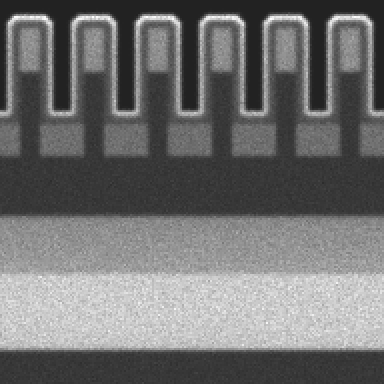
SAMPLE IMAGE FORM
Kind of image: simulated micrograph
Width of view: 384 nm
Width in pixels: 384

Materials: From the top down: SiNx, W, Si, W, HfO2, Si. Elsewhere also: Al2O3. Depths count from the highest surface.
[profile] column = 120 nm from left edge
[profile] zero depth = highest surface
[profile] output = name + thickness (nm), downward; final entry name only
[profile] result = empty 96, SiNx 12, Al2O3 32, Si 60, W 58, HfO2 76, Si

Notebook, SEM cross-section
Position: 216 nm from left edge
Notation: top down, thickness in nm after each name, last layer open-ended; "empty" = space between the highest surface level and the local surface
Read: SiNx 12, W 44, Si 144, W 58, HfO2 76, Si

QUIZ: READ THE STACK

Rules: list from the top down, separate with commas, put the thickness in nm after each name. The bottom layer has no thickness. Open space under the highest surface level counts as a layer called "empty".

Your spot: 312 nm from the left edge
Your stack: empty 96, SiNx 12, Al2O3 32, Si 60, W 58, HfO2 76, Si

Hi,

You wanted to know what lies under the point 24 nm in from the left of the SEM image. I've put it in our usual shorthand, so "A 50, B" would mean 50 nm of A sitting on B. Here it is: SiNx 12, W 44, Si 144, W 58, HfO2 76, Si